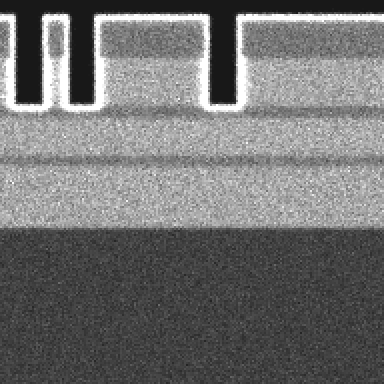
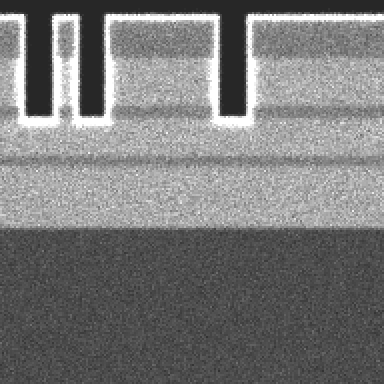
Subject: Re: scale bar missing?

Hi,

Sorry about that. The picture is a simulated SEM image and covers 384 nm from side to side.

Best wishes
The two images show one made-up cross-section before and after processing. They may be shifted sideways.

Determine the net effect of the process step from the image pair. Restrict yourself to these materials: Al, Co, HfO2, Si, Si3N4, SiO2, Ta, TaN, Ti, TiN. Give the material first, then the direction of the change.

Si3N4: removed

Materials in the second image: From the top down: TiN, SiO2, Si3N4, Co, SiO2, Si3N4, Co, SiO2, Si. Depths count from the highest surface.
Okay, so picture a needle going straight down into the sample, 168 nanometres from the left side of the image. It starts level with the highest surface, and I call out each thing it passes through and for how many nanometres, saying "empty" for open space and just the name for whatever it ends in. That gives TiN 42, SiO2 48, Si3N4 12, Co 24, SiO2 14, Si3N4 10, Co 38, SiO2 24, Si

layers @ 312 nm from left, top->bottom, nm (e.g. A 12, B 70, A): TiN 42, SiO2 48, Si3N4 12, Co 24, SiO2 14, Si3N4 10, Co 38, SiO2 24, Si